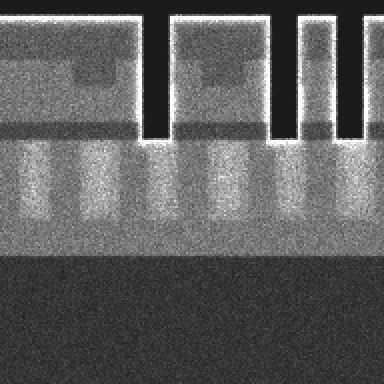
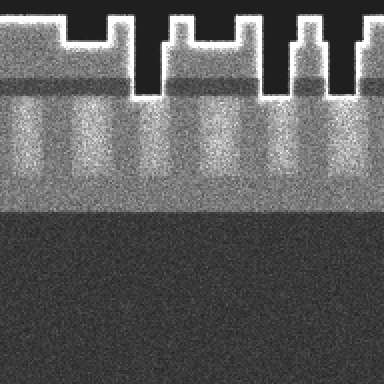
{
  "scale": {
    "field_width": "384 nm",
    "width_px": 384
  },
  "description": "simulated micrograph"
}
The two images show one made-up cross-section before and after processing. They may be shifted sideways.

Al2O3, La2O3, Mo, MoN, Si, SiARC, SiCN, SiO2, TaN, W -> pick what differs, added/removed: SiARC removed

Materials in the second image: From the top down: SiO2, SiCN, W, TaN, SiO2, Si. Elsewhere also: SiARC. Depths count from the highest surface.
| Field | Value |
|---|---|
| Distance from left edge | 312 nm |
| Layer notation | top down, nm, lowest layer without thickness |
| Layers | SiO2 62, SiCN 18, SiO2 116, Si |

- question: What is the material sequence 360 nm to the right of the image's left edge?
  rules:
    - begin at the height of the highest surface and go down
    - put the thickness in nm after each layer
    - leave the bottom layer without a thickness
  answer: empty 26, SiO2 36, SiCN 18, TaN 80, SiO2 36, Si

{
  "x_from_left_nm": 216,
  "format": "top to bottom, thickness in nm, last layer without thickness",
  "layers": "empty 26, SiO2 36, SiCN 18, W 70, TaN 10, SiO2 36, Si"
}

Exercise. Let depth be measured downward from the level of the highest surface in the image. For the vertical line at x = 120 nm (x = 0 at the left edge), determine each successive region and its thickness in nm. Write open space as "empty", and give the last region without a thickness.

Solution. SiO2 62, SiCN 18, SiO2 116, Si